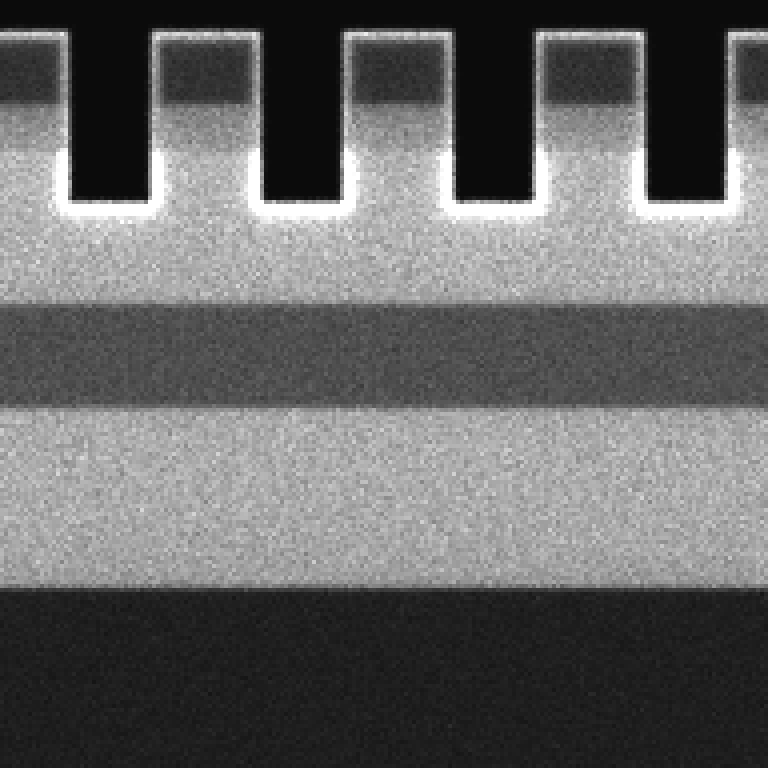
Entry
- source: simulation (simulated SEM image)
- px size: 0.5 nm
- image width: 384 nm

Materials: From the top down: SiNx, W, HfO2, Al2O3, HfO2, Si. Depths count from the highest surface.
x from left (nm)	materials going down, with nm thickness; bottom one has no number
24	SiNx 36, W 24, HfO2 76, Al2O3 52, HfO2 90, Si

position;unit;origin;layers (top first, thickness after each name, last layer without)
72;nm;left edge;empty 86, HfO2 50, Al2O3 52, HfO2 90, Si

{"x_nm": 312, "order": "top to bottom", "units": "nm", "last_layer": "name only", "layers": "SiNx 36, W 24, HfO2 76, Al2O3 52, HfO2 90, Si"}